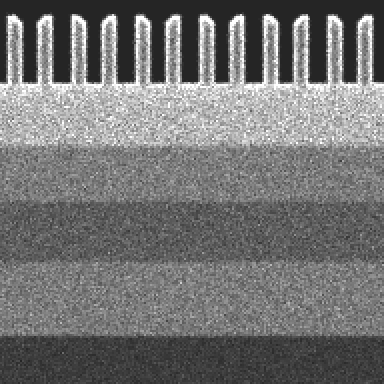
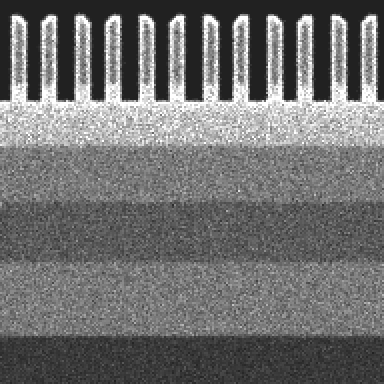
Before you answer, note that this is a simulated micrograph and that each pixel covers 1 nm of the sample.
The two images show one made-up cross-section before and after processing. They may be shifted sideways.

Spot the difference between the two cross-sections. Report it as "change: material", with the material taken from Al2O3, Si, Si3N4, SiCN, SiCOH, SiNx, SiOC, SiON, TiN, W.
removed: W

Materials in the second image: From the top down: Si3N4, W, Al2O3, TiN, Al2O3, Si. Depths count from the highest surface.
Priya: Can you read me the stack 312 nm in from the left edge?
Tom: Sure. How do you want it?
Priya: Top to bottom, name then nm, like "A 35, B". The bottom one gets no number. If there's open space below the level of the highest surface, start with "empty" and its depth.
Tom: empty 86, W 44, Al2O3 56, TiN 60, Al2O3 74, Si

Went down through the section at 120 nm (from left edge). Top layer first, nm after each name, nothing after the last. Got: empty 86, W 44, Al2O3 56, TiN 60, Al2O3 74, Si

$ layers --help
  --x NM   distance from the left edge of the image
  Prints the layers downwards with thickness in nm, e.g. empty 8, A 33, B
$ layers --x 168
empty 86, W 44, Al2O3 56, TiN 60, Al2O3 74, Si